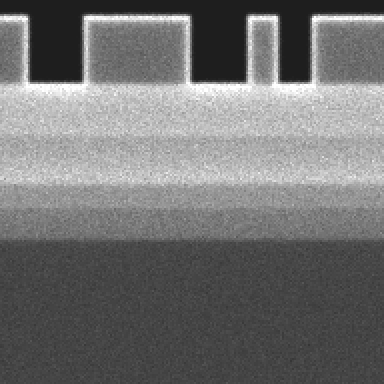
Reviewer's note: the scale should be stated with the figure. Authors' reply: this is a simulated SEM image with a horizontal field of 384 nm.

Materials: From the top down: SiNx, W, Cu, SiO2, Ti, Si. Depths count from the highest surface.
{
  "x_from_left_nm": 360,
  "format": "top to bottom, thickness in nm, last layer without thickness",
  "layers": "SiNx 68, W 52, Cu 48, SiO2 24, Ti 32, Si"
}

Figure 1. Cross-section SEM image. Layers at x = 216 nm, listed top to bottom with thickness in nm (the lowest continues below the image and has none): empty 68, W 52, Cu 48, SiO2 24, Ti 32, Si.